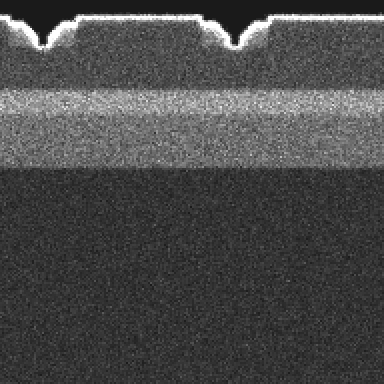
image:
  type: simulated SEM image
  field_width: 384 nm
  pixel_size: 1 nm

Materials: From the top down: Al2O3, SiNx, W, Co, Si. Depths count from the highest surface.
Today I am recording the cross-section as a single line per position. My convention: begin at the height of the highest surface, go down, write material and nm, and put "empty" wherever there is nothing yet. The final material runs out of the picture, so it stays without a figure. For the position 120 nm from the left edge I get SiNx 74, W 24, Co 54, Si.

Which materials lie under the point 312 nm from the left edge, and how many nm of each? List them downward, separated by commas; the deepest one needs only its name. SiNx 74, W 24, Co 54, Si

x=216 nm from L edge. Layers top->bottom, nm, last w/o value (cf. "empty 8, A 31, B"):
empty 8, Al2O3 22, SiNx 44, W 24, Co 54, Si